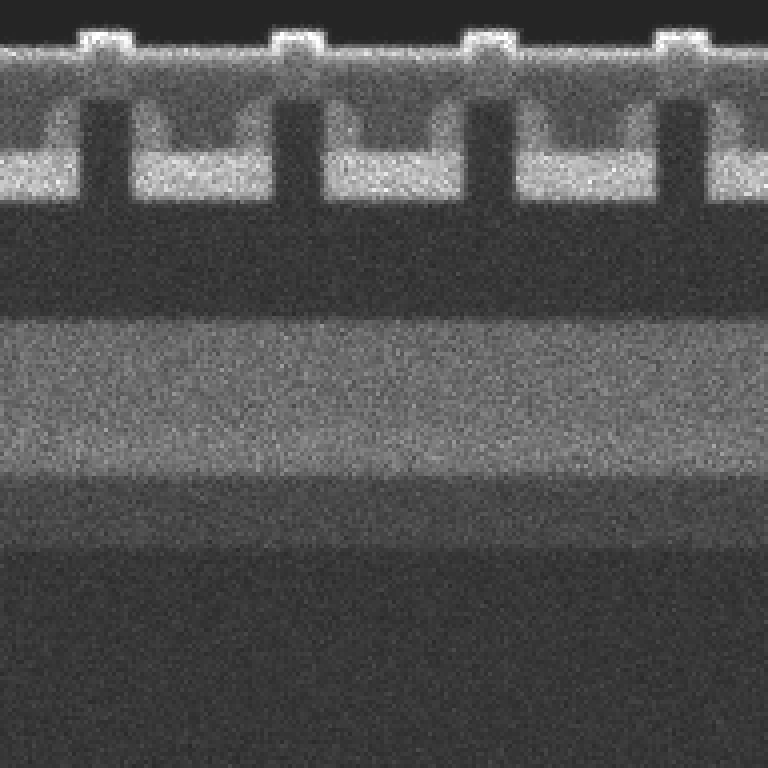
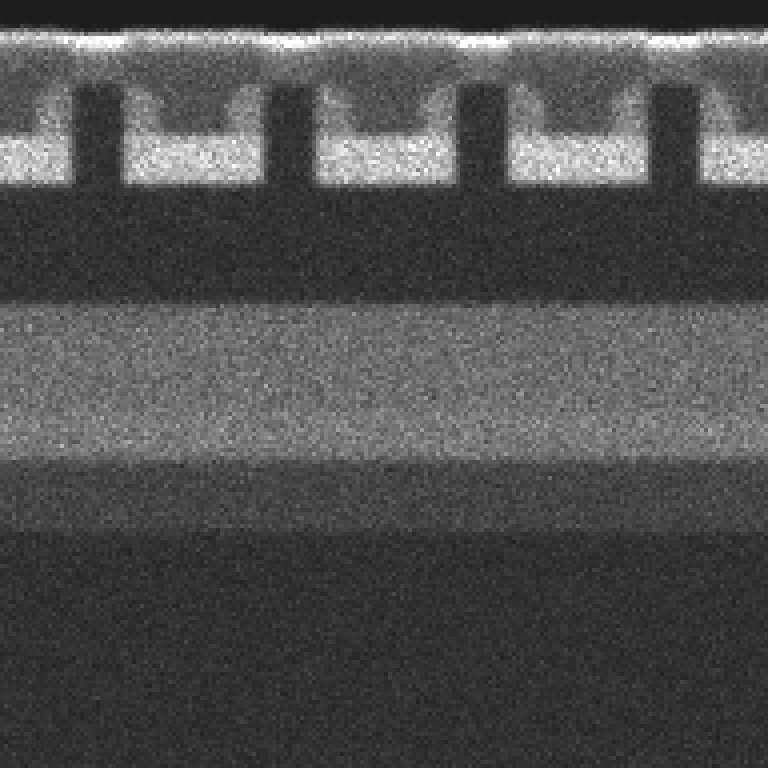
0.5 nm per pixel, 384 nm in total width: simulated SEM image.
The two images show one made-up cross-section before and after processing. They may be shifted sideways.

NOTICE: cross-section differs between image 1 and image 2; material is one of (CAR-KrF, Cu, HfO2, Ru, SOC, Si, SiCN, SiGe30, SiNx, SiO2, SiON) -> removed: SiO2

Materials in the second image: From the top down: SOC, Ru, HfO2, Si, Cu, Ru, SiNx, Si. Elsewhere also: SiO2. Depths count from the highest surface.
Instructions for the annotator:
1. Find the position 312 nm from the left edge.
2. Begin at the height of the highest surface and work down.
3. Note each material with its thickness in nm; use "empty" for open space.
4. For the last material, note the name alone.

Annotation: SOC 28, Ru 24, HfO2 24, Si 60, Cu 54, Ru 24, SiNx 36, Si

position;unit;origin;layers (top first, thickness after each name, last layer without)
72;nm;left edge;SOC 28, Ru 24, HfO2 24, Si 60, Cu 54, Ru 24, SiNx 36, Si